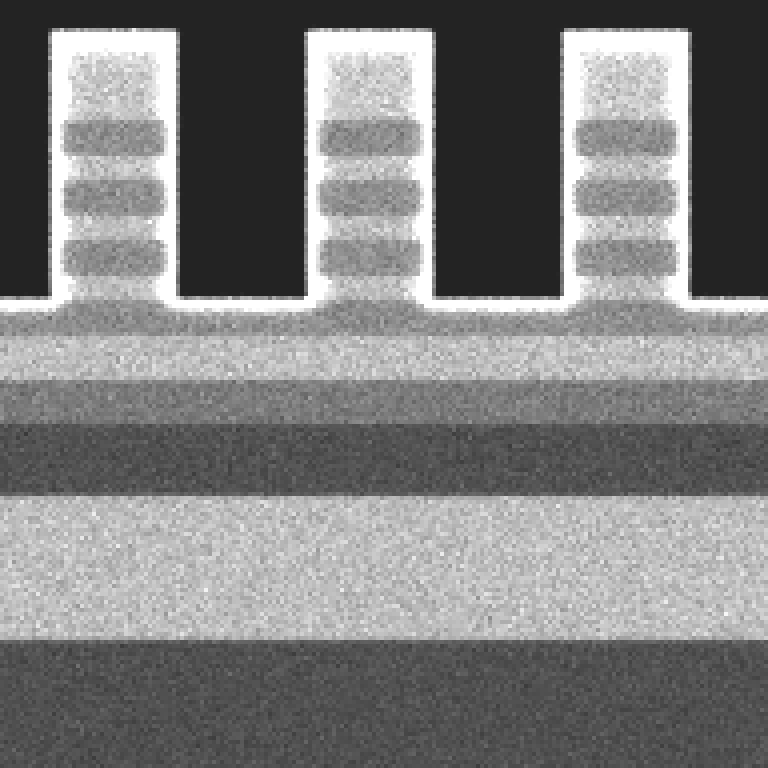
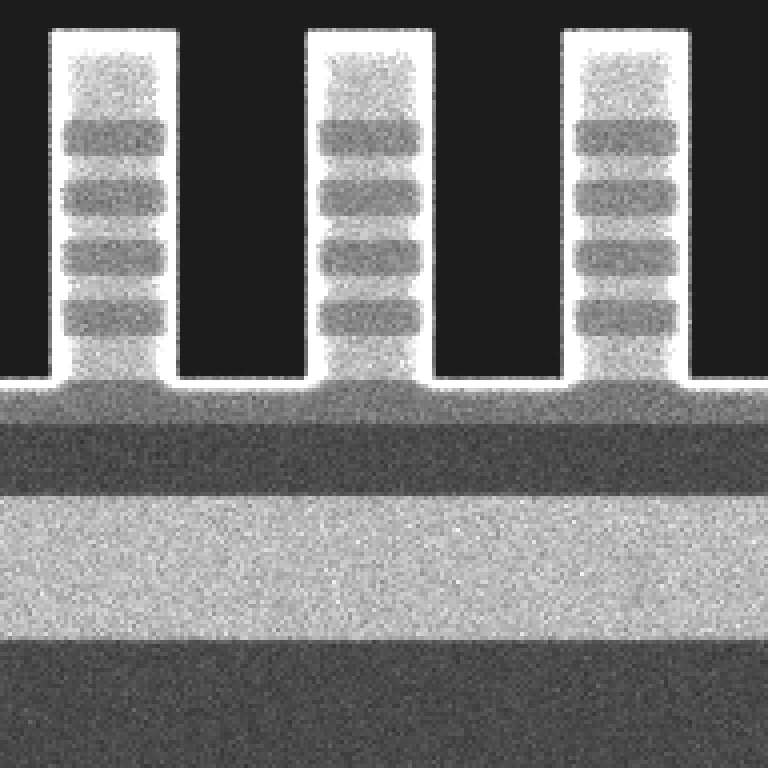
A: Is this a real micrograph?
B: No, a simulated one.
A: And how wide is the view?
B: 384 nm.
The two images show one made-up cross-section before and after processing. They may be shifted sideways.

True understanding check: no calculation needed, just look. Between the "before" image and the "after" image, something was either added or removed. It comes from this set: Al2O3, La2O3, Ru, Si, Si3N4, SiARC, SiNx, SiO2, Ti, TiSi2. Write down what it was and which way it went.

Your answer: Si3N4 and SiO2 (removed)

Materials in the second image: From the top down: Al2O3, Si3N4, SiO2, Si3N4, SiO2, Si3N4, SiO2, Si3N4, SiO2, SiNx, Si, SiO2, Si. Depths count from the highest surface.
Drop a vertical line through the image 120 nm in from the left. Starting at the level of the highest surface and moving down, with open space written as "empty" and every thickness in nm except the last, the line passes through empty 174, SiNx 22, Si 36, SiO2 72, Si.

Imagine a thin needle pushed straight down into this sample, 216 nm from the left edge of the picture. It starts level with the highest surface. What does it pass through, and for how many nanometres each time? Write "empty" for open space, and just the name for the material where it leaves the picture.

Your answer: empty 174, SiNx 22, Si 36, SiO2 72, Si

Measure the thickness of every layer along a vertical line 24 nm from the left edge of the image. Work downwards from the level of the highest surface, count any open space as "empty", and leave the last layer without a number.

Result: empty 174, SiNx 22, Si 36, SiO2 72, Si